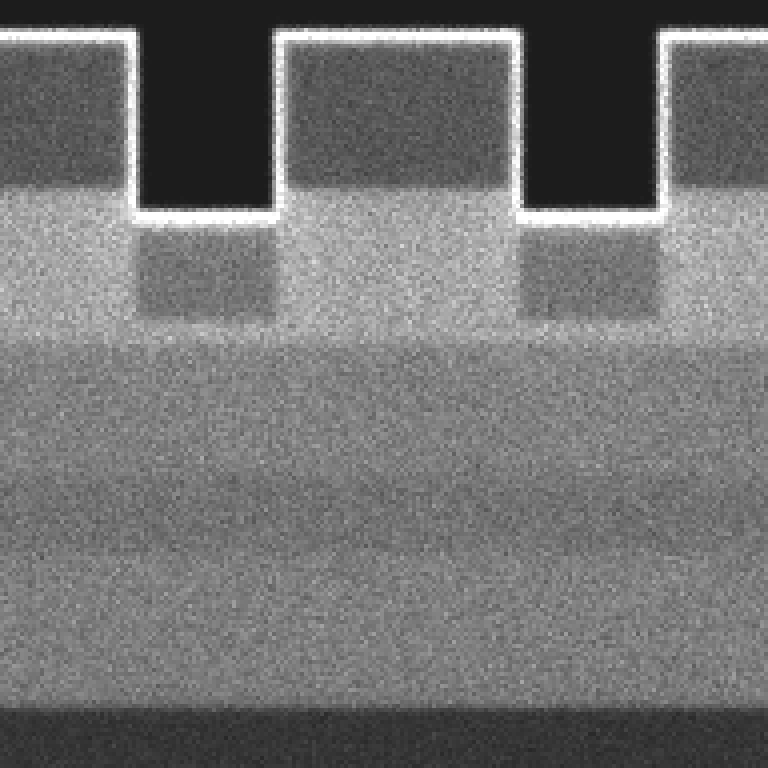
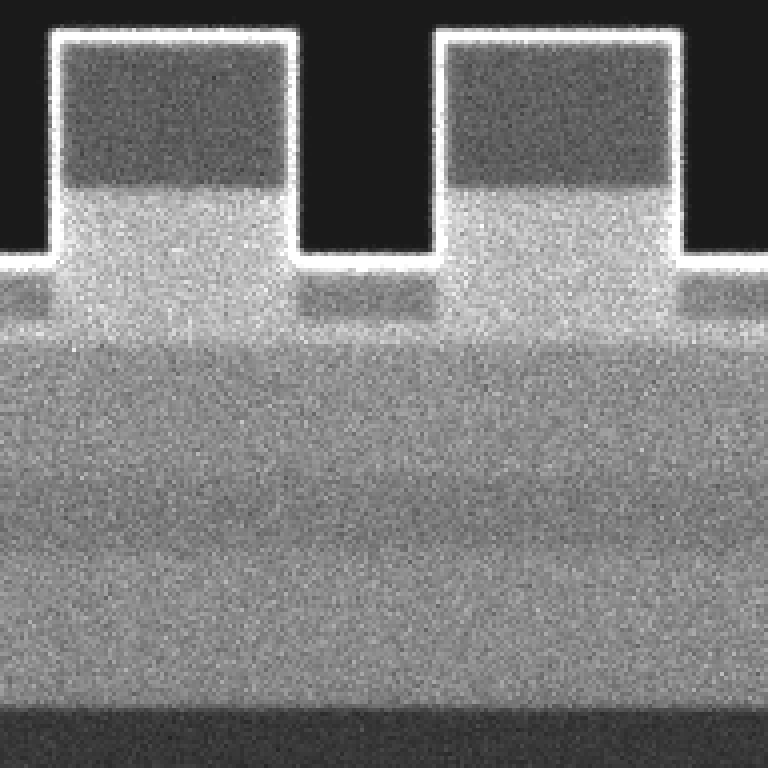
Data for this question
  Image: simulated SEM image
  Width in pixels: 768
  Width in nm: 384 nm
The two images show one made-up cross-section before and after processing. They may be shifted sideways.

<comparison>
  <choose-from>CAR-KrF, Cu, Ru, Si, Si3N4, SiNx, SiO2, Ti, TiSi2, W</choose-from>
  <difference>SiO2 removed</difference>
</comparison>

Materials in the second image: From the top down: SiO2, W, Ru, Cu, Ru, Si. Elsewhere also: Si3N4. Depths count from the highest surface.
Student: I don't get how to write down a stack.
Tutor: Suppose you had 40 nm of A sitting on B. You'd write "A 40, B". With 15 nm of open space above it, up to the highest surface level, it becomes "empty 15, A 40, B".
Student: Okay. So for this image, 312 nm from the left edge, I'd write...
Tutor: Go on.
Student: Si3N4 78, W 78, Ru 66, Cu 38, Ru 78, Si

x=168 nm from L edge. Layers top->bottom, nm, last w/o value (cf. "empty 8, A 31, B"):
empty 112, SiO2 32, W 12, Ru 66, Cu 38, Ru 78, Si